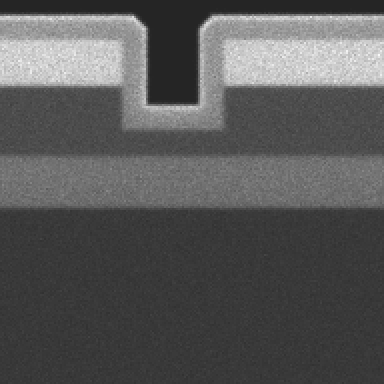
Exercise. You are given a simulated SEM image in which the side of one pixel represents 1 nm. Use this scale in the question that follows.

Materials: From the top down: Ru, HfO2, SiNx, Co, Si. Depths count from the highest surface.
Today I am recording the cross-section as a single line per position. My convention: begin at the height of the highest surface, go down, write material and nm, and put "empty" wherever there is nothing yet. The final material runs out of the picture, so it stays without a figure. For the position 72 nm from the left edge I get Ru 24, HfO2 46, SiNx 70, Co 52, Si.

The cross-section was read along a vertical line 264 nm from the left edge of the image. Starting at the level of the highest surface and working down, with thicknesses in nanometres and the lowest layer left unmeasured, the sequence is Ru 24, HfO2 46, SiNx 70, Co 52, Si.